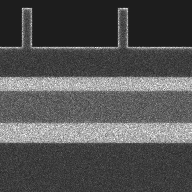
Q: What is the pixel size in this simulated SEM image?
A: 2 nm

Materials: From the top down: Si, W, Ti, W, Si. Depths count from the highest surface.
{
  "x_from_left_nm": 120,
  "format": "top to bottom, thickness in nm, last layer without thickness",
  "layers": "empty 78, Si 60, W 28, Ti 64, W 40, Si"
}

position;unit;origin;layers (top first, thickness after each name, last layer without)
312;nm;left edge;empty 78, Si 60, W 28, Ti 64, W 40, Si